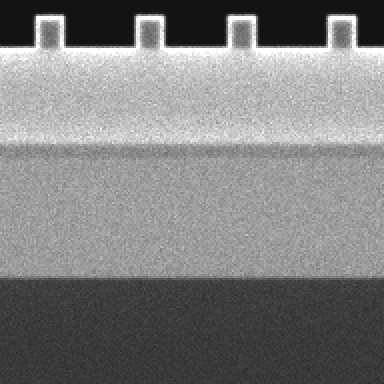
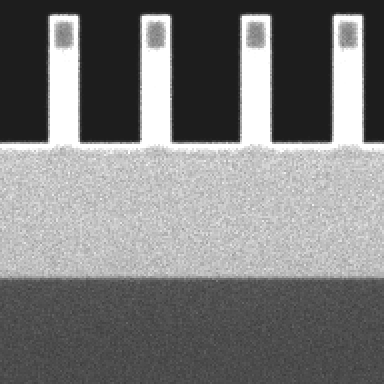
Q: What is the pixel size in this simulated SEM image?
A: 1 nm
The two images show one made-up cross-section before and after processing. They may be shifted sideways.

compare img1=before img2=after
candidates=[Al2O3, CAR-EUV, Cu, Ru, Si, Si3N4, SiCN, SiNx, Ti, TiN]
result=removed:Ru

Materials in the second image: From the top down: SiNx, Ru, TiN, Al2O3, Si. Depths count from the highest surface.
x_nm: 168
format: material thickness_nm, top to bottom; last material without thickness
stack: SiNx 32, Ru 96, TiN 14, Al2O3 120, Si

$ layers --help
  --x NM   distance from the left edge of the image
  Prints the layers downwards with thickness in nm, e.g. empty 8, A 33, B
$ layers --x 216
empty 128, TiN 14, Al2O3 120, Si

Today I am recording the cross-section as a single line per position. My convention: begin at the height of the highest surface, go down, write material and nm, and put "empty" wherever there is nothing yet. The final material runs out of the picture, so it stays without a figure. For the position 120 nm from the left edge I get empty 128, TiN 14, Al2O3 120, Si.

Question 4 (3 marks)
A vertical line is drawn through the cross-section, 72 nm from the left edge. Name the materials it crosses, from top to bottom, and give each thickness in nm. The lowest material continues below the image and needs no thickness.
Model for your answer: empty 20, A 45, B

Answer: SiNx 32, Ru 96, TiN 14, Al2O3 120, Si